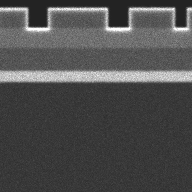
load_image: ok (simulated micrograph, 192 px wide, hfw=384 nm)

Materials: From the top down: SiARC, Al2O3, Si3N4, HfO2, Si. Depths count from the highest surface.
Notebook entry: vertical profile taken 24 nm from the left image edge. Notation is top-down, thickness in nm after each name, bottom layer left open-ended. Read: SiARC 40, Al2O3 40, Si3N4 46, HfO2 22, Si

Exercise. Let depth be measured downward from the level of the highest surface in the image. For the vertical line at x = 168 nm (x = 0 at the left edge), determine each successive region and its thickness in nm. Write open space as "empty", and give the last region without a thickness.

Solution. SiARC 40, Al2O3 40, Si3N4 46, HfO2 22, Si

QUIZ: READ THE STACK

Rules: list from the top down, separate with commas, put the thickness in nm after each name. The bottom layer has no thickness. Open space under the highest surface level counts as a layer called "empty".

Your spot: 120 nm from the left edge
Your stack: SiARC 40, Al2O3 40, Si3N4 46, HfO2 22, Si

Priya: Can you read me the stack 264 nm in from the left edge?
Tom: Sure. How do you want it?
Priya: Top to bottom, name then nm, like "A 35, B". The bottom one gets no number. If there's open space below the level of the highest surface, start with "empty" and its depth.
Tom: SiARC 40, Al2O3 40, Si3N4 46, HfO2 22, Si